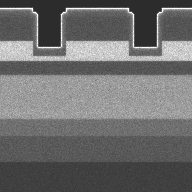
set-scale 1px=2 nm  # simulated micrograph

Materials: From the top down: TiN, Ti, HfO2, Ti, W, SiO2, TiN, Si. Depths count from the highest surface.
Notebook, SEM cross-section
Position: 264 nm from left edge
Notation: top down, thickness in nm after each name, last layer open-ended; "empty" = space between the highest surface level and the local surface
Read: empty 10, TiN 86, HfO2 10, Ti 28, W 88, SiO2 34, TiN 52, Si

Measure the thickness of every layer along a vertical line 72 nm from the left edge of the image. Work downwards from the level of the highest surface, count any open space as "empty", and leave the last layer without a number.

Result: empty 10, TiN 86, HfO2 10, Ti 28, W 88, SiO2 34, TiN 52, Si